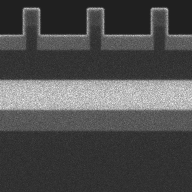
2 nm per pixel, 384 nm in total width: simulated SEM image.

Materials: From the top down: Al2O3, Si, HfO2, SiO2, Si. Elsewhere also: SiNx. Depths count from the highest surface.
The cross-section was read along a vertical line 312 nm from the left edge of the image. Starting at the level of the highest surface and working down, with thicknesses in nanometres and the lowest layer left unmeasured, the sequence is SiNx 36, Si 108, HfO2 60, SiO2 42, Si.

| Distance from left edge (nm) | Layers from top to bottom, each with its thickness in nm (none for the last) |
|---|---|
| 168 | empty 54, Al2O3 30, Si 60, HfO2 60, SiO2 42, Si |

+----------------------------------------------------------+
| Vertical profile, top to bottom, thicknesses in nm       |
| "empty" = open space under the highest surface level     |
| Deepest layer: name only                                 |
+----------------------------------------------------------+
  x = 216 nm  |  empty 54, Al2O3 30, Si 60, HfO2 60, SiO2 42, Si